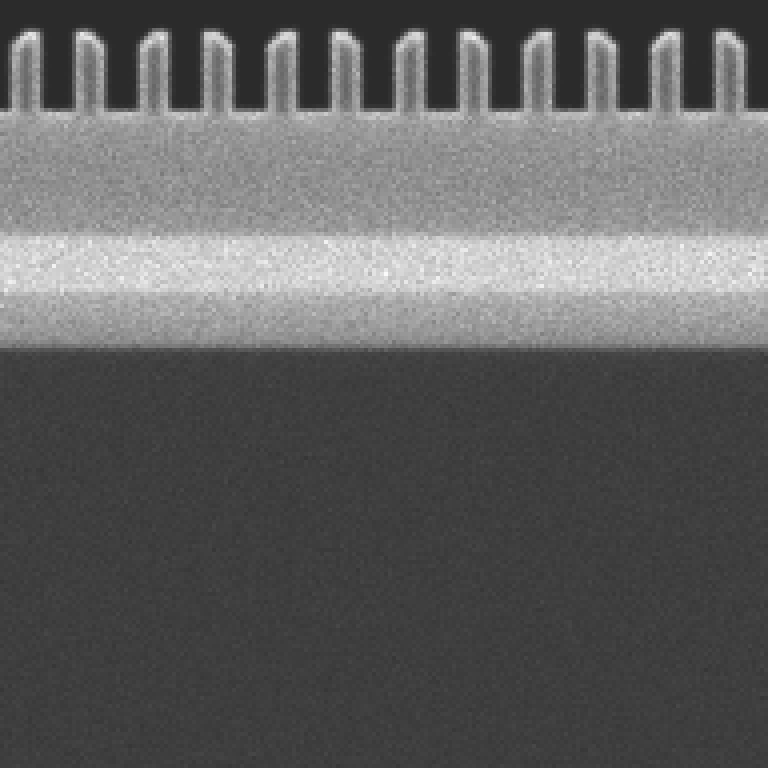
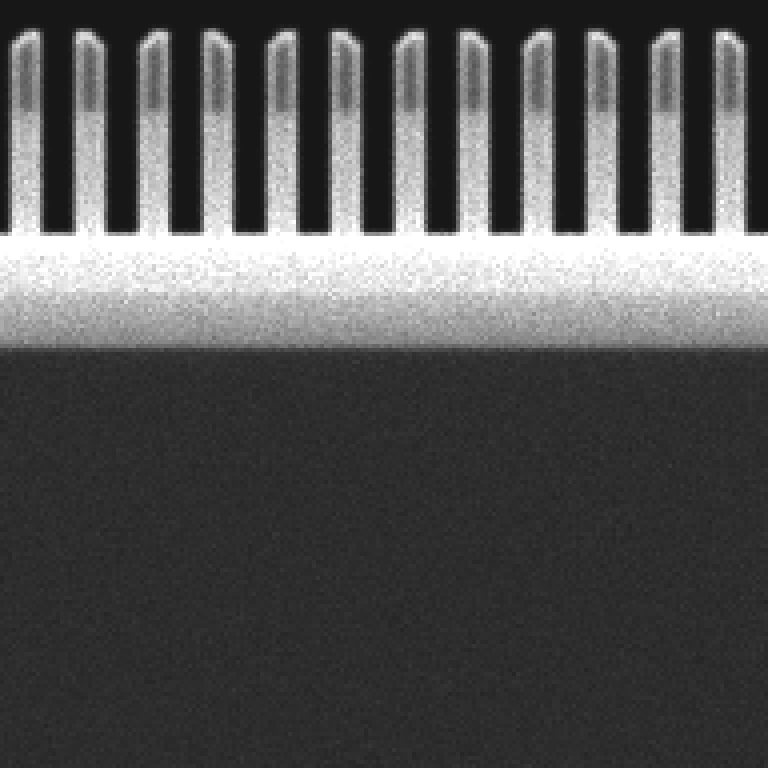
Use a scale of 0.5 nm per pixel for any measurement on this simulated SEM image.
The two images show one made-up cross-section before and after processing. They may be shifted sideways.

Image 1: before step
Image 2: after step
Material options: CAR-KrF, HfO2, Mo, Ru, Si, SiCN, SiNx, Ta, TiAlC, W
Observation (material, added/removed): Ru, removed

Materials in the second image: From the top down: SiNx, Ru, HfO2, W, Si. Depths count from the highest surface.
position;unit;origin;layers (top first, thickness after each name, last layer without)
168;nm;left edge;SiNx 40, Ru 62, HfO2 28, W 28, Si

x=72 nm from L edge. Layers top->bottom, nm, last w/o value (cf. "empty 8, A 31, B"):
empty 4, SiNx 36, Ru 62, HfO2 28, W 28, Si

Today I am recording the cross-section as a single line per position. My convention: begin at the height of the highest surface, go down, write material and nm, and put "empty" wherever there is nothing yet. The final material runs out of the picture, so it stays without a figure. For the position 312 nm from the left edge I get empty 102, HfO2 28, W 28, Si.